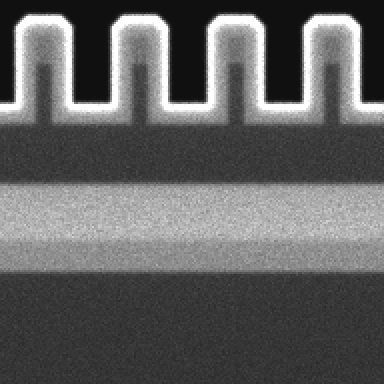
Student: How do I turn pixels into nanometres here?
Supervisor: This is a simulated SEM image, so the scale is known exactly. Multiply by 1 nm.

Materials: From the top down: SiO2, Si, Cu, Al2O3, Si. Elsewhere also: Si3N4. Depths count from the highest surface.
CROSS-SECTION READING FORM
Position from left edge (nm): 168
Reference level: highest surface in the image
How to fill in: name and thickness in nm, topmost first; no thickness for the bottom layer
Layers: empty 88, SiO2 20, Si 60, Cu 56, Al2O3 32, Si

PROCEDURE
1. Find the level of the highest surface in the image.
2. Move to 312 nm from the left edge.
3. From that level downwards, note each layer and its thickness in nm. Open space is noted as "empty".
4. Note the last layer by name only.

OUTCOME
empty 2, SiO2 106, Si 60, Cu 56, Al2O3 32, Si